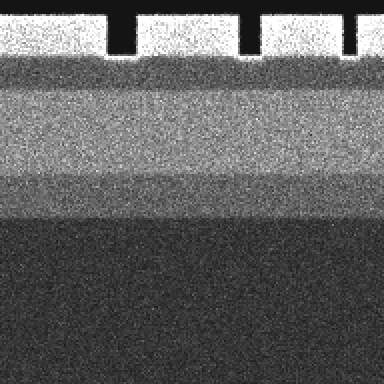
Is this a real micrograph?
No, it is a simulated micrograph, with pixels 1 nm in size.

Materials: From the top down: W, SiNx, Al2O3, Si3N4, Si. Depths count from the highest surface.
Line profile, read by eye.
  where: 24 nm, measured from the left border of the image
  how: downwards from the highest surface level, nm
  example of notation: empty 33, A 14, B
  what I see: W 40, SiNx 34, Al2O3 84, Si3N4 44, Si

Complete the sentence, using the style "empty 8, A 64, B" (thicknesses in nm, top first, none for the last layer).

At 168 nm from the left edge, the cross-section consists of W 40, SiNx 34, Al2O3 84, Si3N4 44, Si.